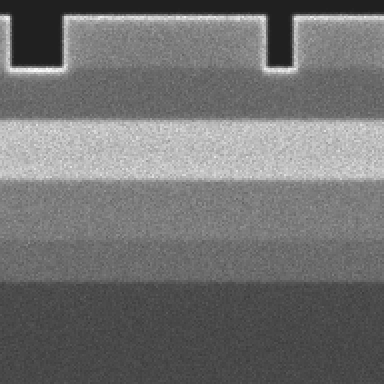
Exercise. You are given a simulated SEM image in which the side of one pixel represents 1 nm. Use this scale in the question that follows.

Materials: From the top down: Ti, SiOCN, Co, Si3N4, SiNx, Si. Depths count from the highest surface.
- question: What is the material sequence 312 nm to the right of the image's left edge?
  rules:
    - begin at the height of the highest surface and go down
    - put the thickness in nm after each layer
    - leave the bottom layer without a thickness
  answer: Ti 52, SiOCN 52, Co 60, Si3N4 60, SiNx 42, Si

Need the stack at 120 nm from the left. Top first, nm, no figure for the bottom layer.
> Ti 52, SiOCN 52, Co 60, Si3N4 60, SiNx 42, Si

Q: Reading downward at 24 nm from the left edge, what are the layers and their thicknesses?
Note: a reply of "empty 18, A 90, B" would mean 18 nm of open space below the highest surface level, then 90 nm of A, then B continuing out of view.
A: empty 52, SiOCN 52, Co 60, Si3N4 60, SiNx 42, Si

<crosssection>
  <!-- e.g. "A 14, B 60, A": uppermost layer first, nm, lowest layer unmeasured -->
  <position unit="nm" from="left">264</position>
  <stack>Ti 52, SiOCN 52, Co 60, Si3N4 60, SiNx 42, Si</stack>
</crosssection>